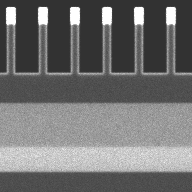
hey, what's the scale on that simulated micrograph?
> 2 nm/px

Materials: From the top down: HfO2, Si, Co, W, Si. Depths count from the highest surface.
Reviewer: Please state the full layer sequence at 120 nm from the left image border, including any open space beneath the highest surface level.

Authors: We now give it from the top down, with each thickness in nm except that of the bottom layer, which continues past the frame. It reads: empty 130, Si 60, Co 88, W 50, Si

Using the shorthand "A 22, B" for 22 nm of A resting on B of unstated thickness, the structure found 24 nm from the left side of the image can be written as HfO2 32, Si 158, Co 88, W 50, Si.